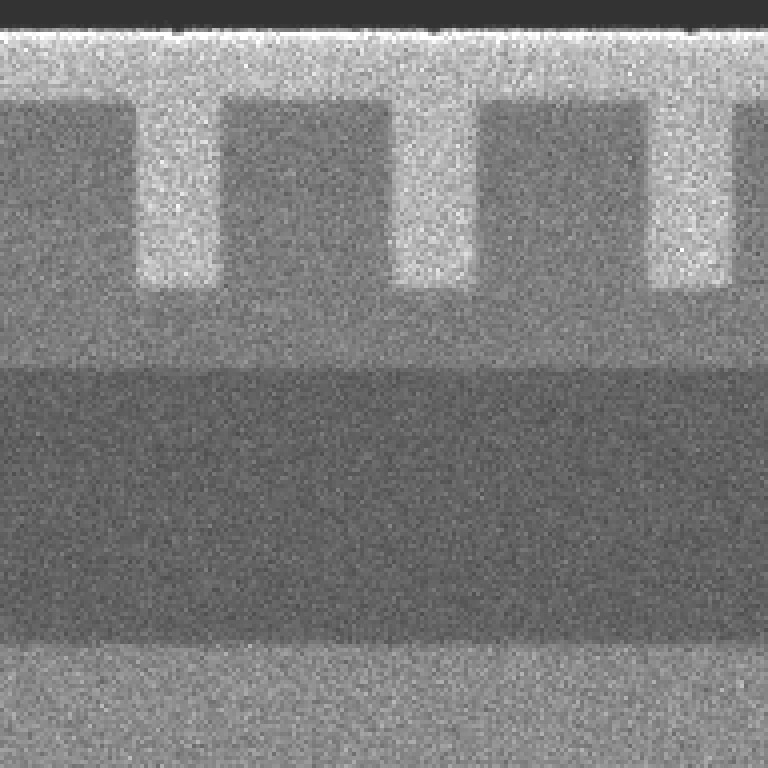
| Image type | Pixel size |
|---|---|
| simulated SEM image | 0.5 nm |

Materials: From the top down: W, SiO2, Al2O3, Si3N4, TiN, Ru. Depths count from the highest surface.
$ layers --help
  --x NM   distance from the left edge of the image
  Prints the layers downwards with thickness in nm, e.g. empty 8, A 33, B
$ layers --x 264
W 34, SiO2 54, Al2O3 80, Si3N4 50, TiN 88, Ru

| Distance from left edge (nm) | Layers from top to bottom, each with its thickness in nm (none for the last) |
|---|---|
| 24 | W 34, SiO2 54, Al2O3 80, Si3N4 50, TiN 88, Ru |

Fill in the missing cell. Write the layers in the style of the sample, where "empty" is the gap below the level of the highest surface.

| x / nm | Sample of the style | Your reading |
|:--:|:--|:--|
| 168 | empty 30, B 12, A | W 34, SiO2 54, Al2O3 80, Si3N4 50, TiN 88, Ru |